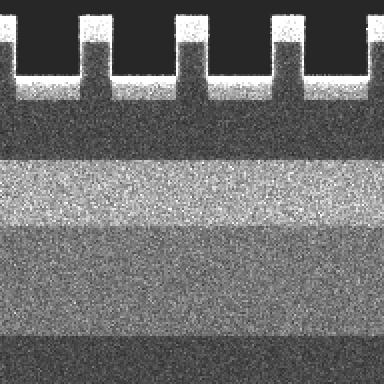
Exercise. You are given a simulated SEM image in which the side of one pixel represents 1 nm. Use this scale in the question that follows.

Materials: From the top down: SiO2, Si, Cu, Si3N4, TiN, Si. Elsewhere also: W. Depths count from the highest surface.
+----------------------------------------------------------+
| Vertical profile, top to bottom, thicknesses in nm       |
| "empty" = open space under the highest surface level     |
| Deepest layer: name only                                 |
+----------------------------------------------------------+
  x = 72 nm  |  empty 60, SiO2 24, Si 60, Cu 66, Si3N4 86, TiN 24, Si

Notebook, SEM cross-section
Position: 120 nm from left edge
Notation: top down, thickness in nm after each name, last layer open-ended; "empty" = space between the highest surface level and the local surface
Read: empty 60, SiO2 24, Si 60, Cu 66, Si3N4 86, TiN 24, Si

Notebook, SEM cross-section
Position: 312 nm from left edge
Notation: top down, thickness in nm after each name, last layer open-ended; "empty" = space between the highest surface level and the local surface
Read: empty 60, SiO2 24, Si 60, Cu 66, Si3N4 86, TiN 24, Si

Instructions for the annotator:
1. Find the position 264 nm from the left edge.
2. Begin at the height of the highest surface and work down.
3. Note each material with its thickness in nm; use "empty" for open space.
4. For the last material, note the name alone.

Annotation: empty 60, SiO2 24, Si 60, Cu 66, Si3N4 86, TiN 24, Si